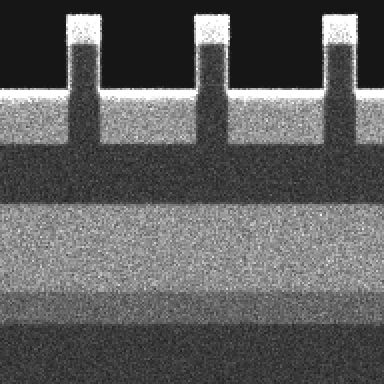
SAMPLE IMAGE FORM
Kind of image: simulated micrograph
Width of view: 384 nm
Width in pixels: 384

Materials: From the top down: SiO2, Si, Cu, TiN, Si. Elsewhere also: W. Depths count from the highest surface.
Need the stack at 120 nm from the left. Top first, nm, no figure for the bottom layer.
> empty 74, SiO2 54, Si 60, Cu 88, TiN 32, Si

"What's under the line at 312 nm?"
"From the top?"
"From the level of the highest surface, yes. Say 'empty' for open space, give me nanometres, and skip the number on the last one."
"empty 74, SiO2 54, Si 60, Cu 88, TiN 32, Si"